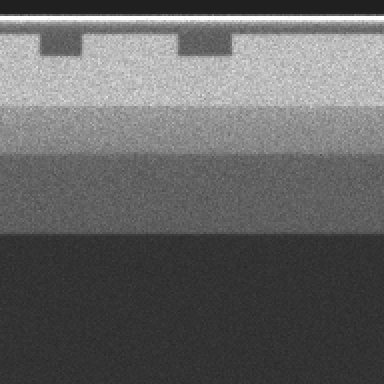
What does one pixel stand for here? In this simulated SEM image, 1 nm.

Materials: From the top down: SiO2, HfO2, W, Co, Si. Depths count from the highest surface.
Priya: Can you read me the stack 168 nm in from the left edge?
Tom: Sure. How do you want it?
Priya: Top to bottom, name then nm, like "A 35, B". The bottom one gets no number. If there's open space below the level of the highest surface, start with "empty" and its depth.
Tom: SiO2 18, HfO2 72, W 48, Co 80, Si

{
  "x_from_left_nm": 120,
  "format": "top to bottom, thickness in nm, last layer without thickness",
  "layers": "SiO2 18, HfO2 72, W 48, Co 80, Si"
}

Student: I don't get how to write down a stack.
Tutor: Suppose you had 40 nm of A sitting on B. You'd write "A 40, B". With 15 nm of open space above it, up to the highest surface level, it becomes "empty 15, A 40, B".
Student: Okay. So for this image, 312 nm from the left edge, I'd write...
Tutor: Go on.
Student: SiO2 18, HfO2 72, W 48, Co 80, Si